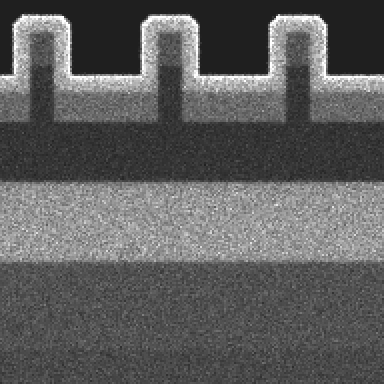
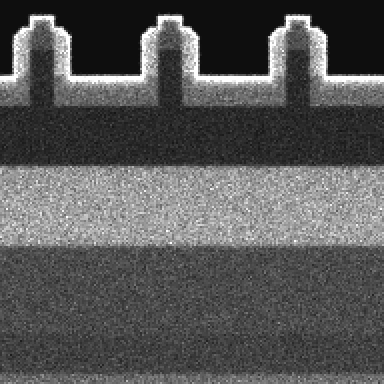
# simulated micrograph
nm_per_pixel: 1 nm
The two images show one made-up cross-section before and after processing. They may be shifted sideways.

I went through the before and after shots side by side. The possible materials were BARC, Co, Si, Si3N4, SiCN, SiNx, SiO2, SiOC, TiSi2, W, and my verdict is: removed, W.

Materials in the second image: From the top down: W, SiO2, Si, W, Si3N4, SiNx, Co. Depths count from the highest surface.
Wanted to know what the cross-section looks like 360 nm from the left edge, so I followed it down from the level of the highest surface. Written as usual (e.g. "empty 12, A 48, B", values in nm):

empty 60, SiO2 30, Si 60, W 80, Si3N4 88, SiNx 40, Co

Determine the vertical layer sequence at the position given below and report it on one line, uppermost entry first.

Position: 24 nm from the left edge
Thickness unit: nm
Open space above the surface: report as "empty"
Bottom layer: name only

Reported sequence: empty 12, W 48, SiO2 30, Si 60, W 80, Si3N4 88, SiNx 40, Co